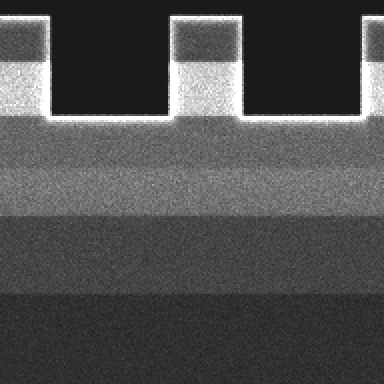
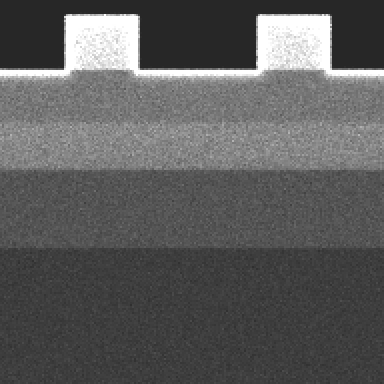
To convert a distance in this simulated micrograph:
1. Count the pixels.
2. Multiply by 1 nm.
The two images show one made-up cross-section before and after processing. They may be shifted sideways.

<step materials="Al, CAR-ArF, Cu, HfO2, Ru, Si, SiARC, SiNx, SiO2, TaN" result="removed SiARC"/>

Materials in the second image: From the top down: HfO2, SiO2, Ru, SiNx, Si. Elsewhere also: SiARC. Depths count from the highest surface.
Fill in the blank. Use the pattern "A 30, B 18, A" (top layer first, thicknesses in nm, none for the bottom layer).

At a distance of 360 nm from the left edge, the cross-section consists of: empty 54, SiO2 52, Ru 48, SiNx 78, Si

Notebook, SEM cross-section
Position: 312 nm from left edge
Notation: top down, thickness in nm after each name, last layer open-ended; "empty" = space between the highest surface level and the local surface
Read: HfO2 54, SiO2 52, Ru 48, SiNx 78, Si